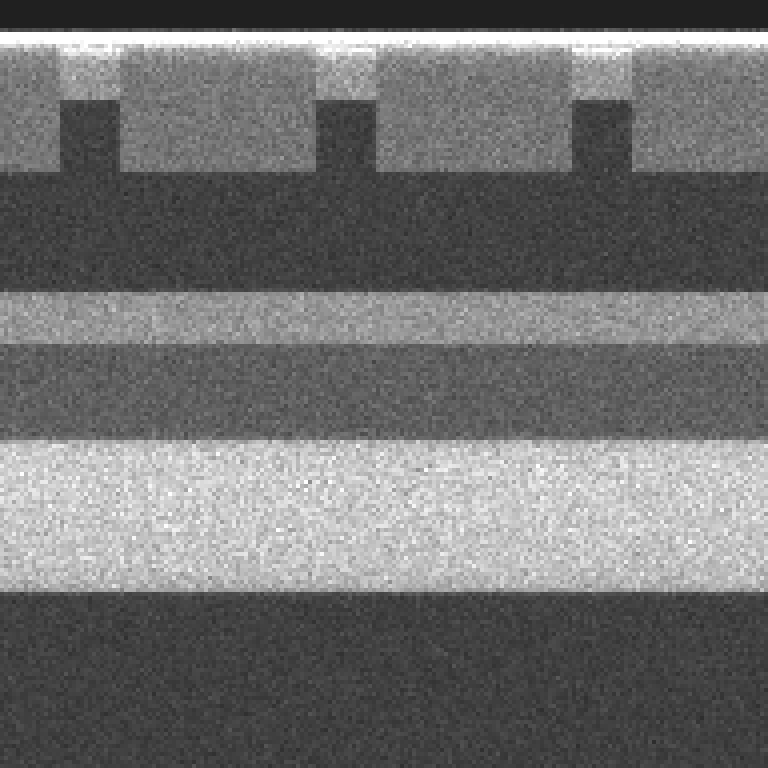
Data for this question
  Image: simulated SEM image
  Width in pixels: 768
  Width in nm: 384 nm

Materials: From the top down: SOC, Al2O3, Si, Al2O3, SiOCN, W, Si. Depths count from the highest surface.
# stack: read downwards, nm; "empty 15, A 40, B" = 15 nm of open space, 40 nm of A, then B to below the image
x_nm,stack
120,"SOC 70, Si 60, Al2O3 26, SiOCN 48, W 76, Si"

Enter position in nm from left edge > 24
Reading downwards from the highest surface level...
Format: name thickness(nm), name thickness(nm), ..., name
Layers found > SOC 70, Si 60, Al2O3 26, SiOCN 48, W 76, Si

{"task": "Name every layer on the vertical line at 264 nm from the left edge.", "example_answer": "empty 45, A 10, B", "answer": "SOC 70, Si 60, Al2O3 26, SiOCN 48, W 76, Si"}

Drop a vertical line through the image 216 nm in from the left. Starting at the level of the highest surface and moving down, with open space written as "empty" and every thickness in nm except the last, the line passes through SOC 70, Si 60, Al2O3 26, SiOCN 48, W 76, Si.